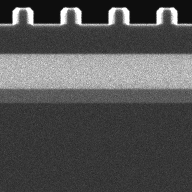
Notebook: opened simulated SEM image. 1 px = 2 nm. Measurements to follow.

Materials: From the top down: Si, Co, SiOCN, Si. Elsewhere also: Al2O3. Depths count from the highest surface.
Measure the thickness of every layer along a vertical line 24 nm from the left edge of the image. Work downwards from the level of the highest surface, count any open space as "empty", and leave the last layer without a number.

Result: empty 32, Si 60, Co 70, SiOCN 28, Si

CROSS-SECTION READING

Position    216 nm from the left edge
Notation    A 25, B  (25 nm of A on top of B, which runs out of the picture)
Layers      empty 32, Si 60, Co 70, SiOCN 28, Si